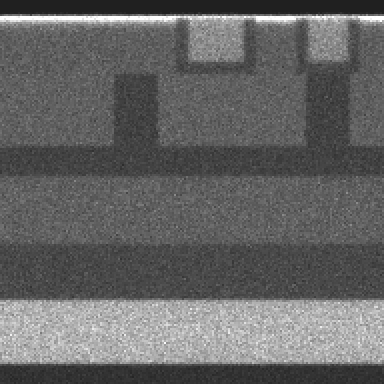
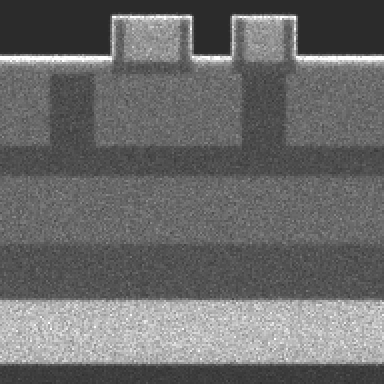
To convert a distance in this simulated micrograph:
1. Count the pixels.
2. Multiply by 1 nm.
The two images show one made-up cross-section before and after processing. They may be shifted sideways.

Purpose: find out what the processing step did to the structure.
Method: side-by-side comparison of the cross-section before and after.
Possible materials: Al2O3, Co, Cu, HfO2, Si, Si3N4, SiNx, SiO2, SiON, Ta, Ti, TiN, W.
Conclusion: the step removed SiO2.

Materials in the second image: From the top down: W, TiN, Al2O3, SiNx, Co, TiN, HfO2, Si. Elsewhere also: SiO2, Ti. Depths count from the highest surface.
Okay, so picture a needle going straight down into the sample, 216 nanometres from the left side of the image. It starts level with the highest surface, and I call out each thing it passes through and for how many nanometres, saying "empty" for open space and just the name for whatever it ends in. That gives empty 40, SiO2 18, Al2O3 72, SiNx 30, Co 68, TiN 56, HfO2 64, Si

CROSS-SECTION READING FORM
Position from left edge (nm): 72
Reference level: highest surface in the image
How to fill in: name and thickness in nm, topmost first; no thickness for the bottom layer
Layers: empty 40, SiO2 18, Ti 84, SiNx 18, Co 68, TiN 56, HfO2 64, Si